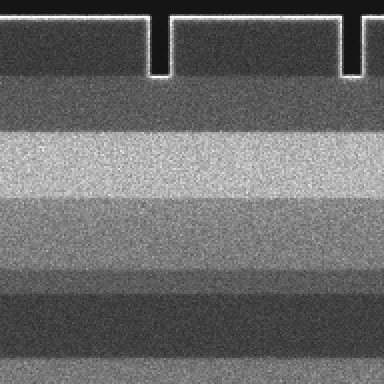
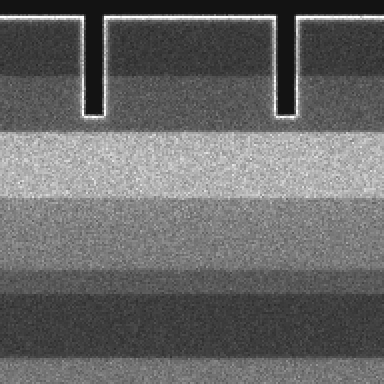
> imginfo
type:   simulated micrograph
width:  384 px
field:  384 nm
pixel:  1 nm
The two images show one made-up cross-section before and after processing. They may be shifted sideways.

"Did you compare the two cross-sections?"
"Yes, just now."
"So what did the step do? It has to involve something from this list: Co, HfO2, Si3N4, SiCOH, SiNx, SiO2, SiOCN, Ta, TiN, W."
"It removed Co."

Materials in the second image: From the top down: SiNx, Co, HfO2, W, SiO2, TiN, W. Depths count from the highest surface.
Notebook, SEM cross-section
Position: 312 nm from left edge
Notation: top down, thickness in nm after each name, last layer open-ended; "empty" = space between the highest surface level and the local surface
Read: SiNx 60, Co 56, HfO2 66, W 72, SiO2 24, TiN 64, W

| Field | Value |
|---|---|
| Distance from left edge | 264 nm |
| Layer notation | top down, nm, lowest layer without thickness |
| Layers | SiNx 60, Co 56, HfO2 66, W 72, SiO2 24, TiN 64, W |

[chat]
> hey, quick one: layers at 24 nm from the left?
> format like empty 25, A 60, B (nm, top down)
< SiNx 60, Co 56, HfO2 66, W 72, SiO2 24, TiN 64, W